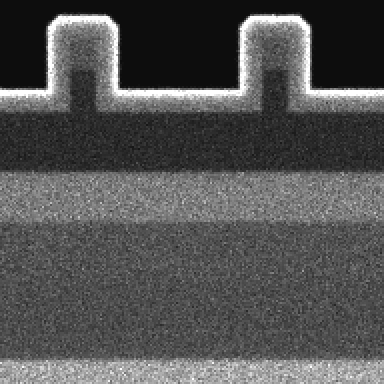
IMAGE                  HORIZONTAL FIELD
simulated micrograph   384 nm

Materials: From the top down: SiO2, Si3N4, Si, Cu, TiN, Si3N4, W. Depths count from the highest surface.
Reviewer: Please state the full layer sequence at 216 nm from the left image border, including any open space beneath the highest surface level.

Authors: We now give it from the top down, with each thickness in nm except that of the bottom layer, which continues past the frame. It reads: empty 74, SiO2 22, Si 60, Cu 50, TiN 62, Si3N4 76, W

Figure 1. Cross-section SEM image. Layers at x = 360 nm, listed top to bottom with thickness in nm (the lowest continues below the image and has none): empty 74, SiO2 22, Si 60, Cu 50, TiN 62, Si3N4 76, W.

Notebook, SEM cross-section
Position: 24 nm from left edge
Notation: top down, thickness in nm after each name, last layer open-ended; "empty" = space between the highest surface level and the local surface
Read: empty 74, SiO2 22, Si 60, Cu 50, TiN 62, Si3N4 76, W